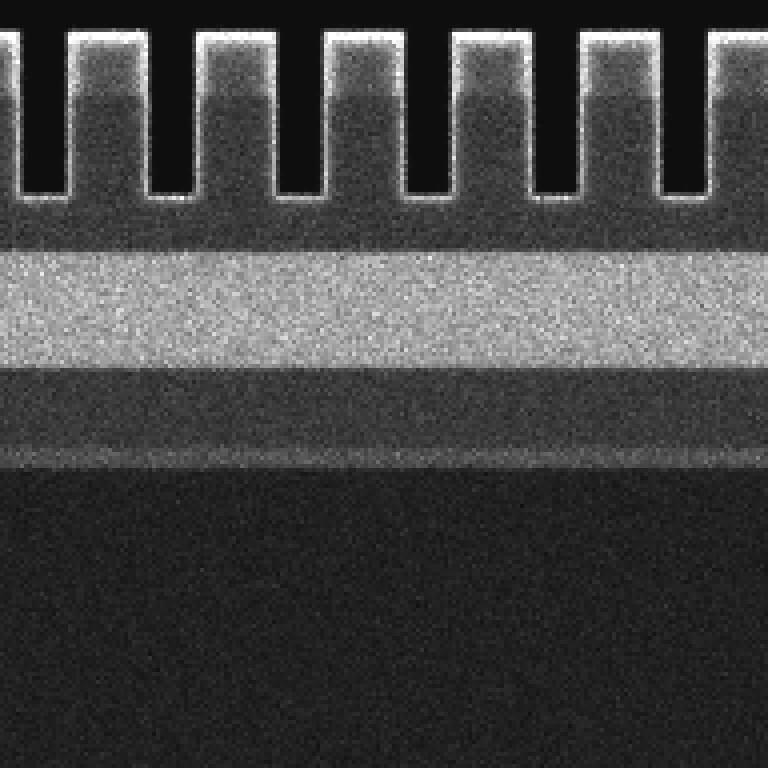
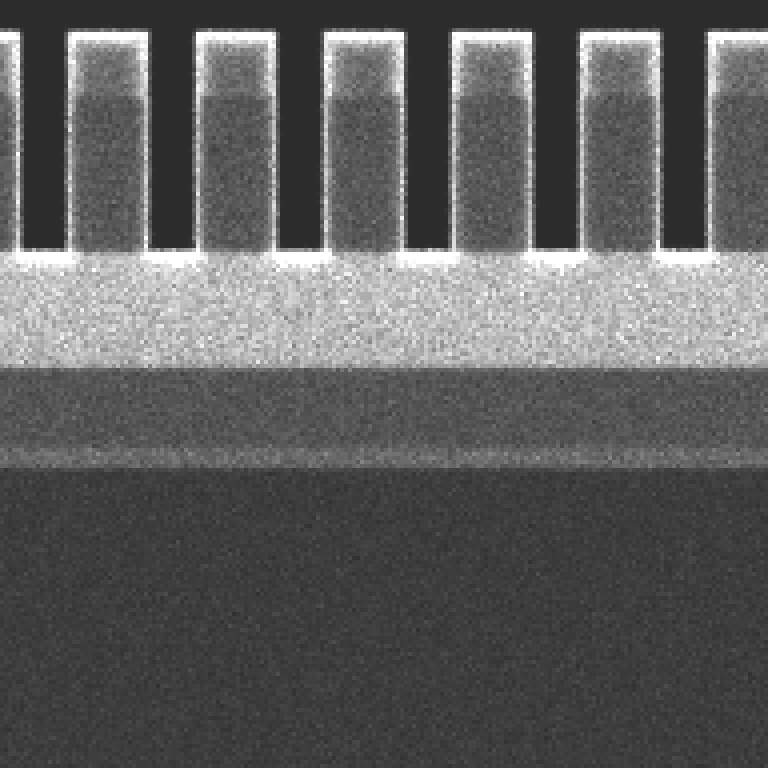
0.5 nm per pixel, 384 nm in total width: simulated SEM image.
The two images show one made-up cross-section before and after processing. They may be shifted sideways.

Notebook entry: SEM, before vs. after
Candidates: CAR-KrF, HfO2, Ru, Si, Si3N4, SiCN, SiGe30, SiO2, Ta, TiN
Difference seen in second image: TiN removed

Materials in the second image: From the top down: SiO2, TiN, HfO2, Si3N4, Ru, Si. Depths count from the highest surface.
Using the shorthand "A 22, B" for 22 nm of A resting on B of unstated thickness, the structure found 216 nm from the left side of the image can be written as empty 110, HfO2 58, Si3N4 40, Ru 10, Si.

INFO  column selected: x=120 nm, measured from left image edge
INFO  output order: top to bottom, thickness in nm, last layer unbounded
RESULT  SiO2 32, TiN 78, HfO2 58, Si3N4 40, Ru 10, Si